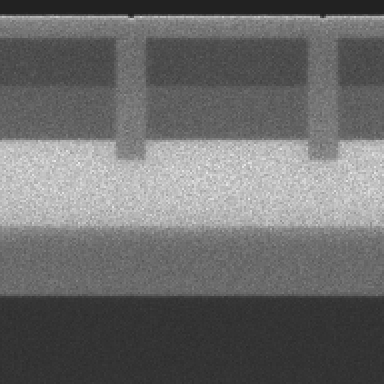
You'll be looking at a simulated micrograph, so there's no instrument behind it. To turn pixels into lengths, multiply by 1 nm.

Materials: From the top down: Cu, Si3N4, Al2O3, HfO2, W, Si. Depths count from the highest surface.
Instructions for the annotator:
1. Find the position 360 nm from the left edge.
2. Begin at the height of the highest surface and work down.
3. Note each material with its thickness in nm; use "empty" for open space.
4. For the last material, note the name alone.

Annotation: Cu 22, Si3N4 48, Al2O3 54, HfO2 86, W 70, Si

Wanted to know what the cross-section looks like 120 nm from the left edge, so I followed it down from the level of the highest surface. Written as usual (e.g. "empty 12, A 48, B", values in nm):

Cu 144, HfO2 66, W 70, Si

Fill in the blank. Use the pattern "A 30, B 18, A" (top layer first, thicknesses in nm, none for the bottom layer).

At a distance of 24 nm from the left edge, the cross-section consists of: Cu 22, Si3N4 48, Al2O3 54, HfO2 86, W 70, Si